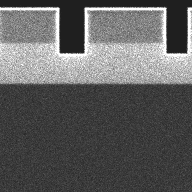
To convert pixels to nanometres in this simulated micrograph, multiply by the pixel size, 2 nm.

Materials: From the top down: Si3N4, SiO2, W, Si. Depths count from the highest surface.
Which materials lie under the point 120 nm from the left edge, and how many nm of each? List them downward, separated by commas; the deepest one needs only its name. empty 92, W 60, Si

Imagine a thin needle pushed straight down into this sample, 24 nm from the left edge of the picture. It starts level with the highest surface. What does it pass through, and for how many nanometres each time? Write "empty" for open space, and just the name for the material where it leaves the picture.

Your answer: Si3N4 10, SiO2 60, W 82, Si